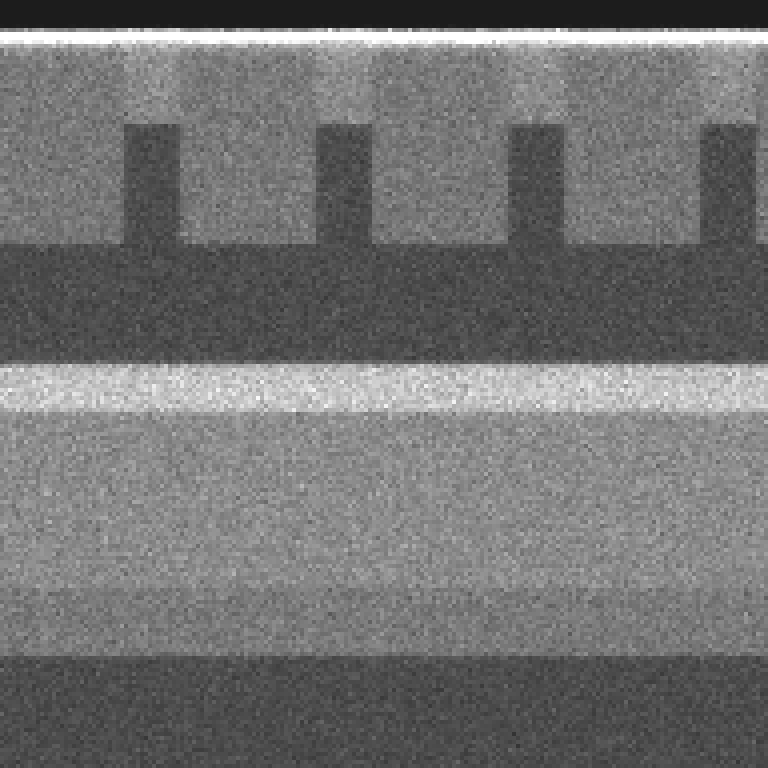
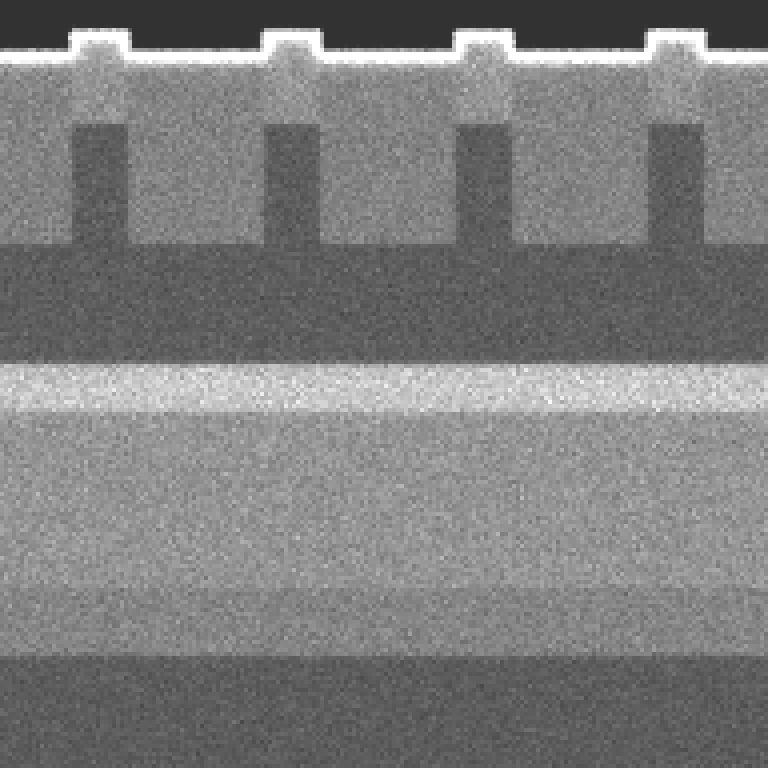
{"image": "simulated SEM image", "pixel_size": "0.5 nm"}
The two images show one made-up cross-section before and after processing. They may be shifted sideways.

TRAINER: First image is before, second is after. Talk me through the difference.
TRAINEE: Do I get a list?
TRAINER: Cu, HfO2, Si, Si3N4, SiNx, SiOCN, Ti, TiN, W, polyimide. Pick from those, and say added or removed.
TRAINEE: removed: SiOCN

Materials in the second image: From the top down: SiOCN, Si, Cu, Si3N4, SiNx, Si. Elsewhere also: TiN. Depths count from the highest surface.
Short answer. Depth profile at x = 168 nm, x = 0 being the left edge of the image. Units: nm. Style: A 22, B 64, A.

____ empty 10, SiOCN 96, Si 60, Cu 24, Si3N4 88, SiNx 34, Si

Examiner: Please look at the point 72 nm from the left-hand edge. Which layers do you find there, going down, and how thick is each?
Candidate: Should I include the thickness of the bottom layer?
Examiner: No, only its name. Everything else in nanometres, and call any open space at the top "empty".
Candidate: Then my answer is empty 10, SiOCN 96, Si 60, Cu 24, Si3N4 88, SiNx 34, Si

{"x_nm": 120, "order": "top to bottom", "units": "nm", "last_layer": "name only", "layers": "empty 10, SiOCN 96, Si 60, Cu 24, Si3N4 88, SiNx 34, Si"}